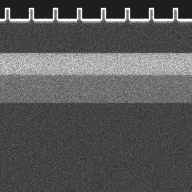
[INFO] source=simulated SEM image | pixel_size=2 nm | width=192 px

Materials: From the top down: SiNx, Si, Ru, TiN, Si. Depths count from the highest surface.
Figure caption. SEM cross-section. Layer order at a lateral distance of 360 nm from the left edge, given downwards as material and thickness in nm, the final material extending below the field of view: empty 22, SiNx 8, Si 60, Ru 44, TiN 56, Si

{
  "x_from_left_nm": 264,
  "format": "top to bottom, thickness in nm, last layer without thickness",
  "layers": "empty 22, SiNx 8, Si 60, Ru 44, TiN 56, Si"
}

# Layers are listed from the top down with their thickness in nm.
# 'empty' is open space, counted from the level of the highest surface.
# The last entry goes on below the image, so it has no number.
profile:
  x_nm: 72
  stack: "empty 22, SiNx 8, Si 60, Ru 44, TiN 56, Si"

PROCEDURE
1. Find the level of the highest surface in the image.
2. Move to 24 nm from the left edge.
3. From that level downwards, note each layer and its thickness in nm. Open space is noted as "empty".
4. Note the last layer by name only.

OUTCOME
empty 22, SiNx 8, Si 60, Ru 44, TiN 56, Si